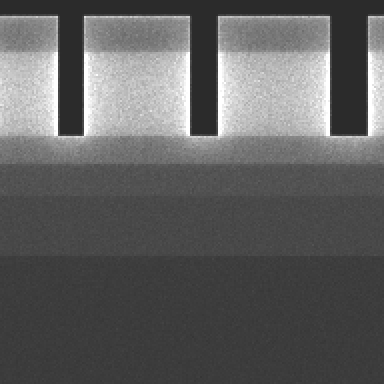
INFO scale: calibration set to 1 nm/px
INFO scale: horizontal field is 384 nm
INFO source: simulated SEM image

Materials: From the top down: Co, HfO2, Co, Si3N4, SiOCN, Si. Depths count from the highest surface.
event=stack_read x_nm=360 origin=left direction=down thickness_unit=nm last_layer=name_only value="empty 120, Co 28, Si3N4 32, SiOCN 60, Si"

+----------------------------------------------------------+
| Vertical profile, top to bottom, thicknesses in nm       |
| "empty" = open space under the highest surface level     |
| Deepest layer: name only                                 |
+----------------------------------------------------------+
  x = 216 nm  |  empty 120, Co 28, Si3N4 32, SiOCN 60, Si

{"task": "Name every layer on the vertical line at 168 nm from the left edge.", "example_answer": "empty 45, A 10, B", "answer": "Co 36, HfO2 84, Co 28, Si3N4 32, SiOCN 60, Si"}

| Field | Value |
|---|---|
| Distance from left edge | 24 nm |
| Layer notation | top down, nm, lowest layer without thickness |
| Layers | Co 36, HfO2 84, Co 28, Si3N4 32, SiOCN 60, Si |